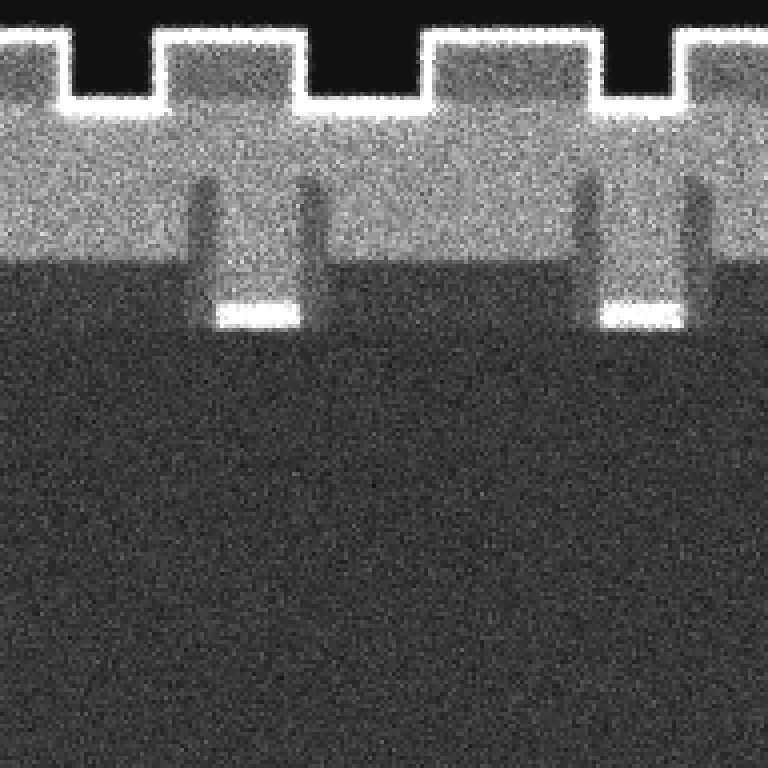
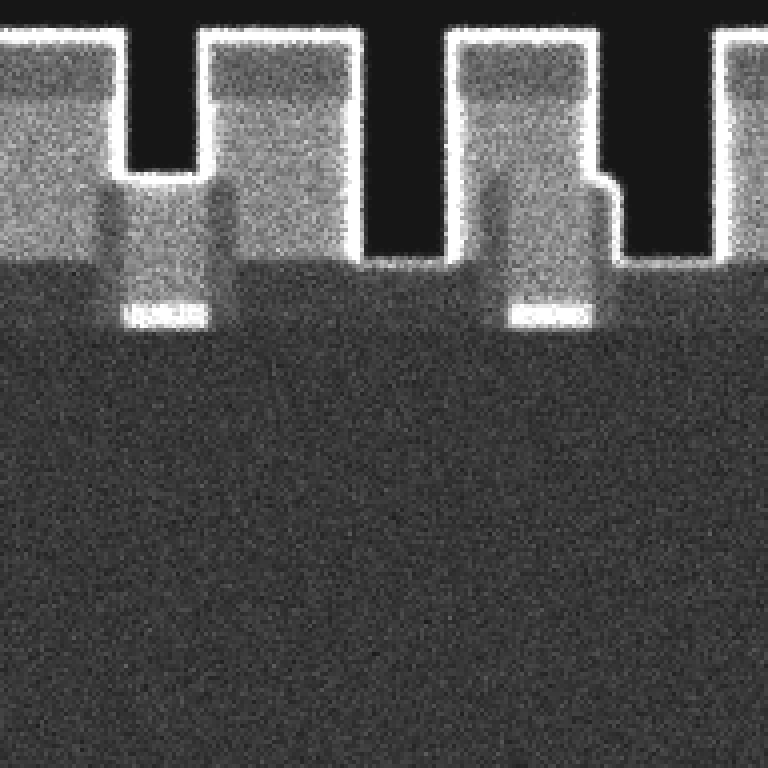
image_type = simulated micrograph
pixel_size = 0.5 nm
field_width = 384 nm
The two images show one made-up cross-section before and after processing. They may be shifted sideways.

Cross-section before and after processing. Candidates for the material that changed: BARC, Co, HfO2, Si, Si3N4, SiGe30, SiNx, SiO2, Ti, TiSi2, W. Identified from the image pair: SiO2 (removed).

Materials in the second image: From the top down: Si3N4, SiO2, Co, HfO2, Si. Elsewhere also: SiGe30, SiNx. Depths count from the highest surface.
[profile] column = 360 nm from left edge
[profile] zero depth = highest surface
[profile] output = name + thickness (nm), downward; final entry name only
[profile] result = Si3N4 34, SiO2 80, SiGe30 34, Si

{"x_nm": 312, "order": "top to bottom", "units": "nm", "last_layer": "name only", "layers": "empty 114, SiGe30 34, Si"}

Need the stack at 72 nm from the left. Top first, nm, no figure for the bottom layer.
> empty 72, Co 64, HfO2 12, Si